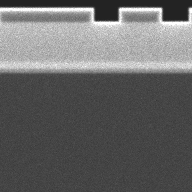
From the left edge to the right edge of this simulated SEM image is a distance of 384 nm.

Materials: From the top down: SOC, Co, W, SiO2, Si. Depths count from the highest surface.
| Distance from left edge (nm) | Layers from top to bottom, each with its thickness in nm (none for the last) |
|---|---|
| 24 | SOC 28, Co 80, W 14, SiO2 8, Si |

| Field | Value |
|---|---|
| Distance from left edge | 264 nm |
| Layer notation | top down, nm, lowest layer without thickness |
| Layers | SOC 28, Co 80, W 14, SiO2 8, Si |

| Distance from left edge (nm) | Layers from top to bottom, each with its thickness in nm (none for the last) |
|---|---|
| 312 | SOC 28, Co 80, W 14, SiO2 8, Si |